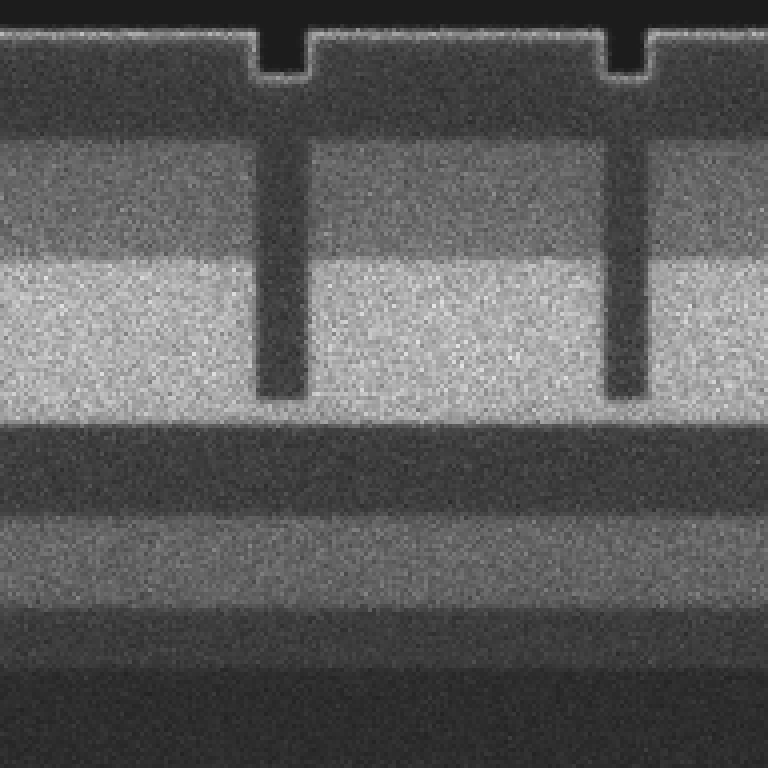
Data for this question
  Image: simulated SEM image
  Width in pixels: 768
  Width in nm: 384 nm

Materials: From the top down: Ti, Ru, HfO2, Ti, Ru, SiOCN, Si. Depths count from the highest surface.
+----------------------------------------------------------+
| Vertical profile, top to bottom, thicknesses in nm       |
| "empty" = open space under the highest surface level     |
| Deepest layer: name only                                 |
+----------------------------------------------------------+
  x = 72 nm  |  Ti 54, Ru 60, HfO2 82, Ti 46, Ru 46, SiOCN 30, Si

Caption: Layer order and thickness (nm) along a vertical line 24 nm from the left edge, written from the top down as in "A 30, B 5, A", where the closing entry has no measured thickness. Ti 54, Ru 60, HfO2 82, Ti 46, Ru 46, SiOCN 30, Si